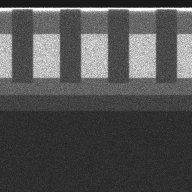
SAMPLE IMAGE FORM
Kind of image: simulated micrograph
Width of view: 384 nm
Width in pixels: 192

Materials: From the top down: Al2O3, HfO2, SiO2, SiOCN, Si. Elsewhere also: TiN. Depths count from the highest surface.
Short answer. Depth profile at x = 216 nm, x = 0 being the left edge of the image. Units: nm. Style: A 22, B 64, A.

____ TiN 150, SiO2 24, SiOCN 32, Si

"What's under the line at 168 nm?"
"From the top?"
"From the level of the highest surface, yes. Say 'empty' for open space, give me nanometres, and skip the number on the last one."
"Al2O3 52, HfO2 88, SiO2 34, SiOCN 32, Si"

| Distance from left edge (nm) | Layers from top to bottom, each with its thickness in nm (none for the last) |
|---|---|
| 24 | TiN 150, SiO2 24, SiOCN 32, Si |